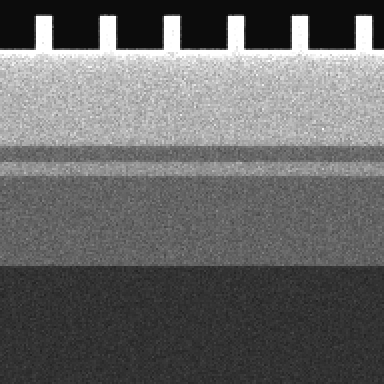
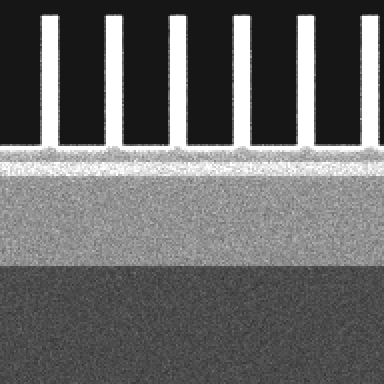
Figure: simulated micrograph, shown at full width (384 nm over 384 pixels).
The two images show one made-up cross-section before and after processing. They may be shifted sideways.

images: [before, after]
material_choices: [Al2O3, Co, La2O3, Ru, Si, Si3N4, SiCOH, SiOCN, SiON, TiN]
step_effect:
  removed: Ru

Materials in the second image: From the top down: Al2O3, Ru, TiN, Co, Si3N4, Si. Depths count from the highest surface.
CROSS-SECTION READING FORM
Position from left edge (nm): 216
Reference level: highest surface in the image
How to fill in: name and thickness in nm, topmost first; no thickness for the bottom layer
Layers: empty 130, TiN 16, Co 14, Si3N4 90, Si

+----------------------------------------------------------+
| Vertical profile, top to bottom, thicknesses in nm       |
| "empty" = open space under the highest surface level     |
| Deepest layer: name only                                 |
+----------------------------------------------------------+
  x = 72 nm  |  empty 130, TiN 16, Co 14, Si3N4 90, Si